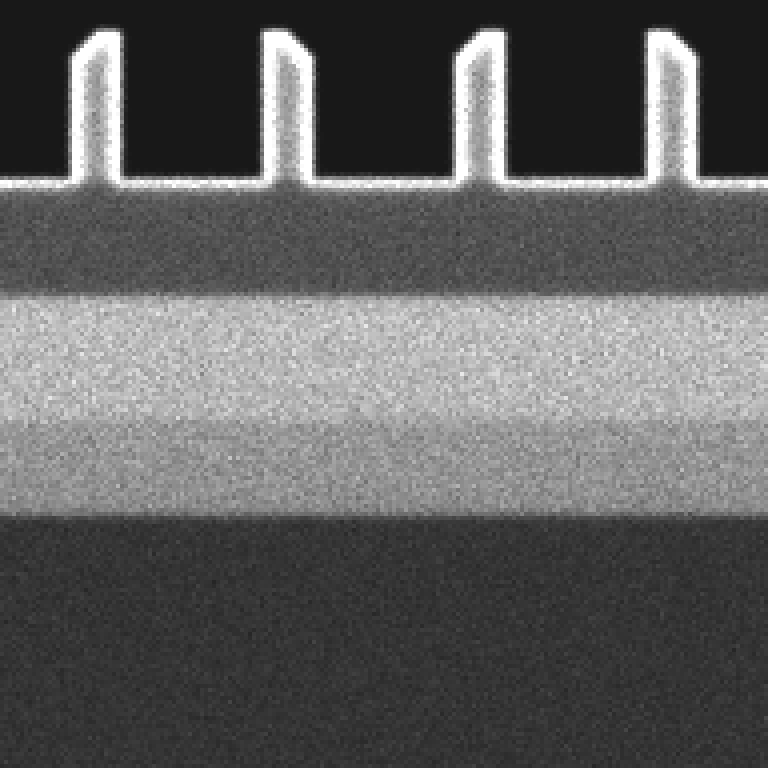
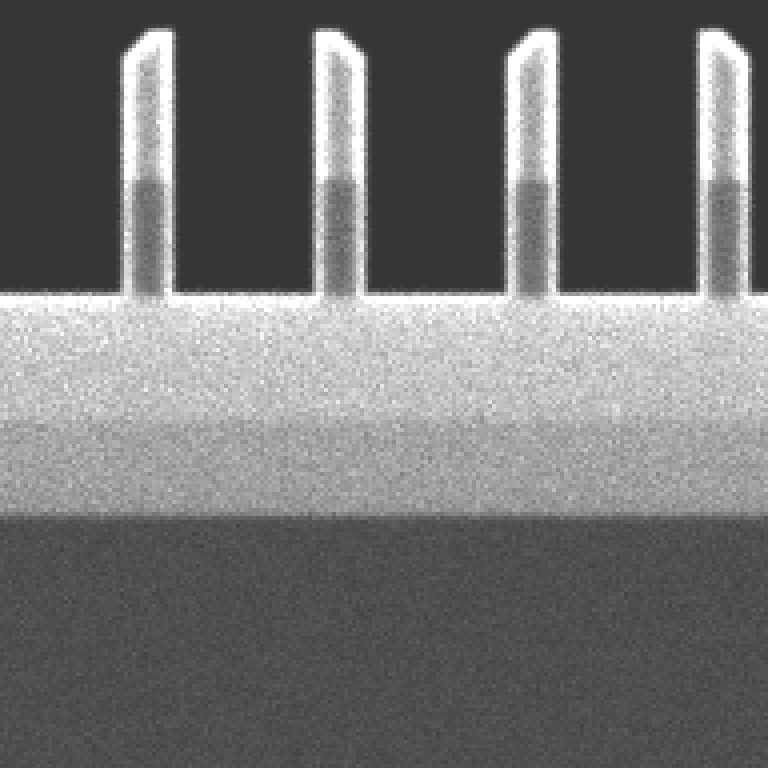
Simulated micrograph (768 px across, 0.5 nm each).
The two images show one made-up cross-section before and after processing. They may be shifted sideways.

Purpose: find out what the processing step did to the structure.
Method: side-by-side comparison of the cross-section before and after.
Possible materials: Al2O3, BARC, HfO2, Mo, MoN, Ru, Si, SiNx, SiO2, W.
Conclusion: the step removed SiNx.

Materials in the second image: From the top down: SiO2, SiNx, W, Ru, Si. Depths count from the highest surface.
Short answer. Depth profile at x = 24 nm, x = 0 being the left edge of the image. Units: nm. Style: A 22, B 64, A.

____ empty 132, W 62, Ru 48, Si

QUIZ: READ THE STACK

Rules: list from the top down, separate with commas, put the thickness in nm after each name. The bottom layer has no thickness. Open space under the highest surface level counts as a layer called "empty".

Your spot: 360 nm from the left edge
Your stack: SiO2 74, SiNx 58, W 62, Ru 48, Si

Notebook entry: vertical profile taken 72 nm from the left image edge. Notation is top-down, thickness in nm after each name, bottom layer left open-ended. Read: empty 2, SiO2 72, SiNx 58, W 62, Ru 48, Si